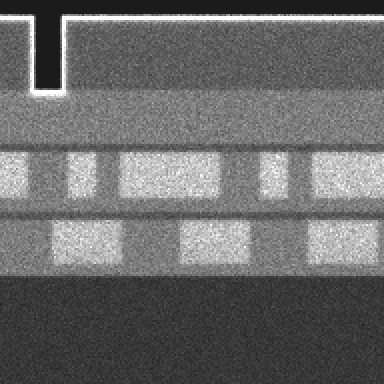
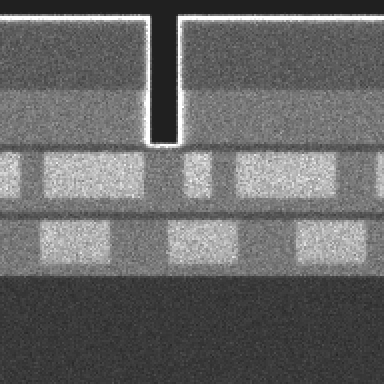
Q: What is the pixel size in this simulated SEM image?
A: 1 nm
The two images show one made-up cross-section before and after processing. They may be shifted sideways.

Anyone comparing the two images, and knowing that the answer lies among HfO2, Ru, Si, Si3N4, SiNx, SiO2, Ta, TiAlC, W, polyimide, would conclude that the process removed SiO2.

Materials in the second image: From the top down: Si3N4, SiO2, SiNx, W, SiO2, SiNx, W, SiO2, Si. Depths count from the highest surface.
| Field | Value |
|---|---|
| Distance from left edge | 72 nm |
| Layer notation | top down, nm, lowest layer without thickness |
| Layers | Si3N4 74, SiO2 54, SiNx 8, W 46, SiO2 14, SiNx 8, W 44, SiO2 12, Si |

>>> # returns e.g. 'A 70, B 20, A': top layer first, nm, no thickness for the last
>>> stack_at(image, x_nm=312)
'Si3N4 74, SiO2 54, SiNx 8, W 46, SiO2 14, SiNx 8, W 44, SiO2 12, Si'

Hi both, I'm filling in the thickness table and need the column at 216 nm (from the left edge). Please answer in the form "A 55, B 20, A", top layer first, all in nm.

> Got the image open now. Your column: Si3N4 74, SiO2 54, SiNx 8, SiO2 60, SiNx 8, W 44, SiO2 12, Si